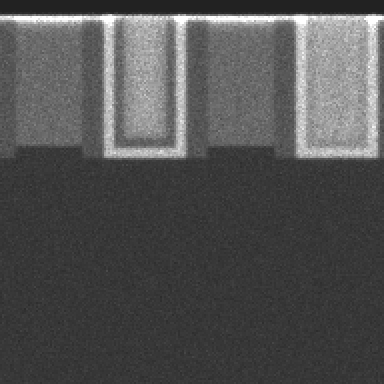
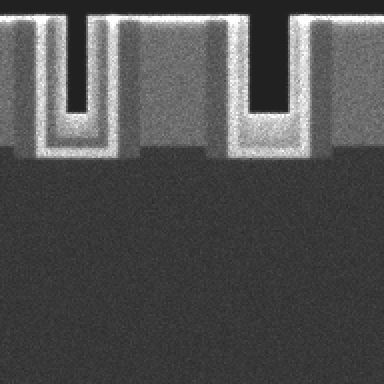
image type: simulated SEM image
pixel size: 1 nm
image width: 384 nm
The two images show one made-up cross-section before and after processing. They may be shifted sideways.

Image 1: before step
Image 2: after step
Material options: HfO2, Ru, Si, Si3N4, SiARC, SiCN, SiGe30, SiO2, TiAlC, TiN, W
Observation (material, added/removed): W, removed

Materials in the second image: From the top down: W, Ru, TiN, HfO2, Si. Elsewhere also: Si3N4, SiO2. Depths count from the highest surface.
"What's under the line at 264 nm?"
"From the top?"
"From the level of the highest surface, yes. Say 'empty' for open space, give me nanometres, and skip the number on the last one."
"empty 98, W 24, Ru 10, HfO2 10, Si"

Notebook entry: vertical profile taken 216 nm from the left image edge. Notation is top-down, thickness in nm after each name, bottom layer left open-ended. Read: Si3N4 142, Si